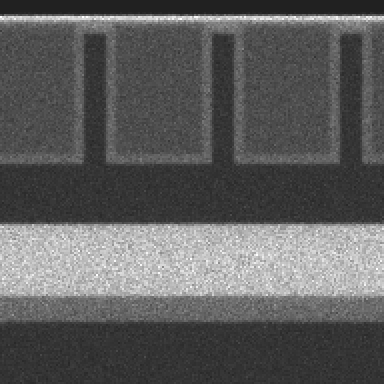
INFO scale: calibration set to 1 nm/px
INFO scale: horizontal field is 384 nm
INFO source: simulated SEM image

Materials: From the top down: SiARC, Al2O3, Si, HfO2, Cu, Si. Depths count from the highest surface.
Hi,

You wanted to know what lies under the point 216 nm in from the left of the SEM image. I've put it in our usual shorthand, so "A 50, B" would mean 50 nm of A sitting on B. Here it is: SiARC 8, Al2O3 10, Si 190, HfO2 72, Cu 26, Si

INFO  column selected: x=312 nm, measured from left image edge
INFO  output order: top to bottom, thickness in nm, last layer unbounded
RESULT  SiARC 138, Al2O3 10, Si 60, HfO2 72, Cu 26, Si